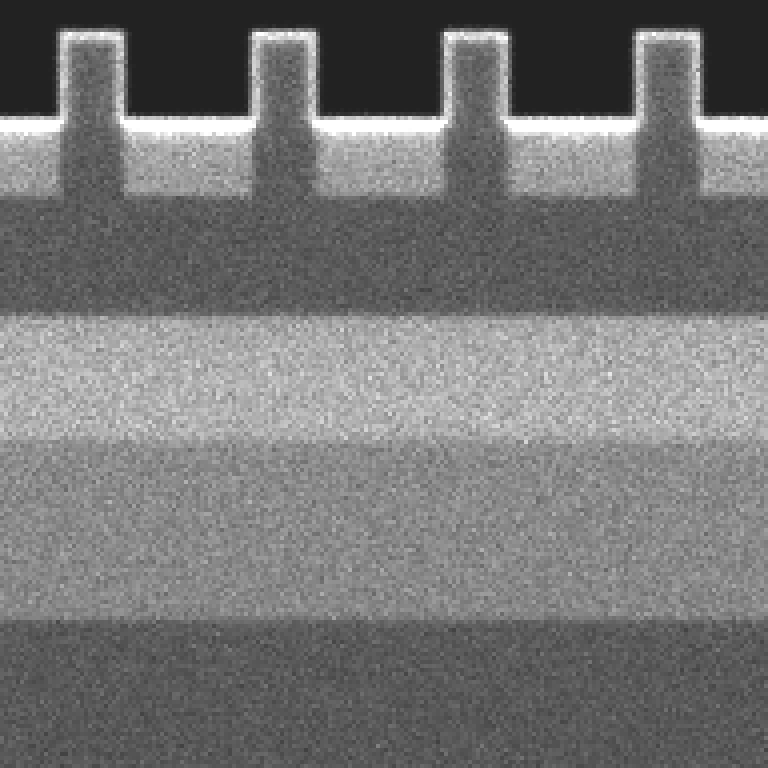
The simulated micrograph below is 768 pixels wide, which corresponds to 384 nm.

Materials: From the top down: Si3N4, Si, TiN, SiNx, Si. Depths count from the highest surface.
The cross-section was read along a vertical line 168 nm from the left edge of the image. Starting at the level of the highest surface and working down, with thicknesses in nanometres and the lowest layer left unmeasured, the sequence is empty 44, Si3N4 38, Si 60, TiN 62, SiNx 90, Si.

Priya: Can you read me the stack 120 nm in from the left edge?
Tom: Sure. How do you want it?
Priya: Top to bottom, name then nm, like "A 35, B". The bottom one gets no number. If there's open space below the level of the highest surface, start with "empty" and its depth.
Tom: empty 44, Si3N4 38, Si 60, TiN 62, SiNx 90, Si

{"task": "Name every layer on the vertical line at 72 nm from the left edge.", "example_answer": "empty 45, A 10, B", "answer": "empty 44, Si3N4 38, Si 60, TiN 62, SiNx 90, Si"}